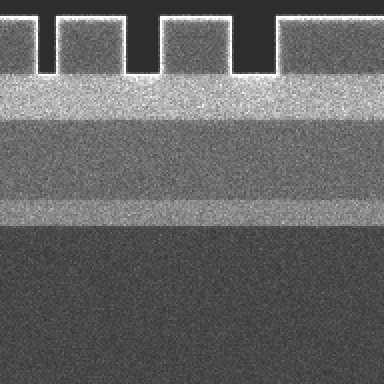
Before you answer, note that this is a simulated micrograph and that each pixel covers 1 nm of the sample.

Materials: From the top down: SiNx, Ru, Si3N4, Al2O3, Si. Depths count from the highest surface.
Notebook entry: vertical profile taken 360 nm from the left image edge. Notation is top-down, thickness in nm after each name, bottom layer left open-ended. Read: SiNx 58, Ru 46, Si3N4 80, Al2O3 26, Si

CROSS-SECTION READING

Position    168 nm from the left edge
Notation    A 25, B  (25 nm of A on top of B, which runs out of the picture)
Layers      SiNx 58, Ru 46, Si3N4 80, Al2O3 26, Si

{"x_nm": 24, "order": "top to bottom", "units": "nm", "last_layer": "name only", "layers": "SiNx 58, Ru 46, Si3N4 80, Al2O3 26, Si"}